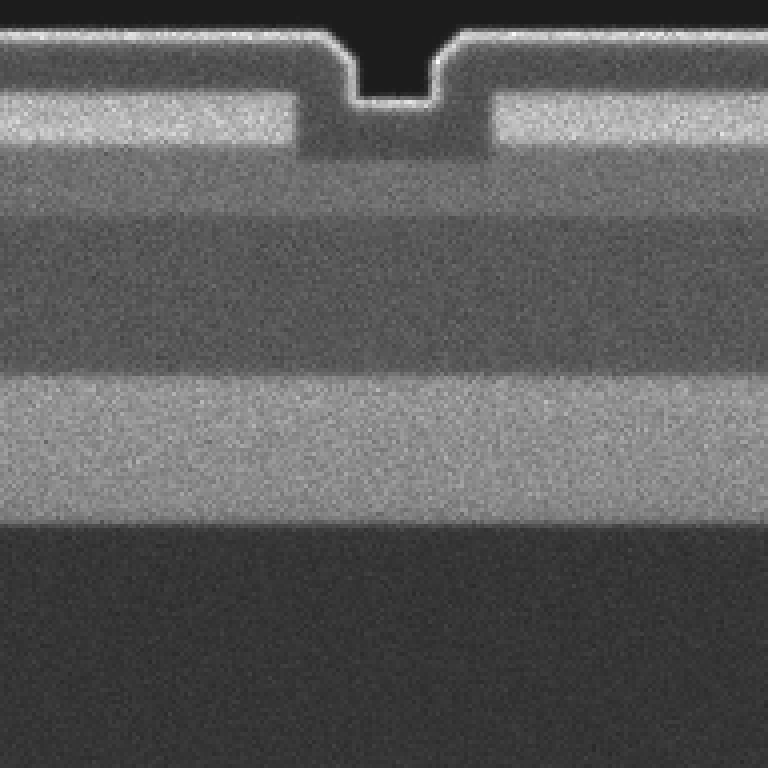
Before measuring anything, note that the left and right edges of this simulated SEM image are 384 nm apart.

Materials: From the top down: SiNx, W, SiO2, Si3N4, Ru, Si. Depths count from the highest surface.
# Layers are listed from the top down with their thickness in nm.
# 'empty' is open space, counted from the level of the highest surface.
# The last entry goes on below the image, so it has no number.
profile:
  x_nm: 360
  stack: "SiNx 30, W 26, SiO2 36, Si3N4 80, Ru 74, Si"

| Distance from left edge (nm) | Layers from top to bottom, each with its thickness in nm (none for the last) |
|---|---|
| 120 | SiNx 30, W 26, SiO2 36, Si3N4 80, Ru 74, Si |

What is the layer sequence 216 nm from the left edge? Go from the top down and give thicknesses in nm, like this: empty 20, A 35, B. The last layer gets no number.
empty 14, SiNx 50, SiO2 28, Si3N4 80, Ru 74, Si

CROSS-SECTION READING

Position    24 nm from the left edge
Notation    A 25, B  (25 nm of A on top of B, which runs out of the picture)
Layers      SiNx 30, W 26, SiO2 36, Si3N4 80, Ru 74, Si